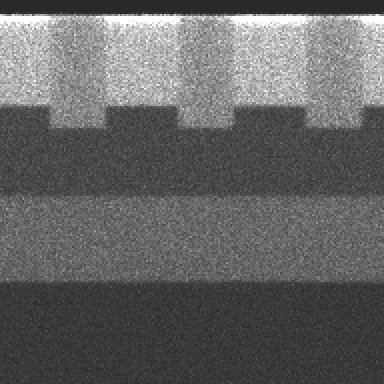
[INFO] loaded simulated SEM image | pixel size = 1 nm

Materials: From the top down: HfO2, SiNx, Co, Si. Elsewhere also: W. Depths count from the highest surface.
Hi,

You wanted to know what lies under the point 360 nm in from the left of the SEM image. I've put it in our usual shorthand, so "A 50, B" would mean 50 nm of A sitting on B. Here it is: W 112, SiNx 68, Co 86, Si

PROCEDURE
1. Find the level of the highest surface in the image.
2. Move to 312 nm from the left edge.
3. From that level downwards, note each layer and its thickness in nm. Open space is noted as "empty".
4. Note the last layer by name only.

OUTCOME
W 112, SiNx 68, Co 86, Si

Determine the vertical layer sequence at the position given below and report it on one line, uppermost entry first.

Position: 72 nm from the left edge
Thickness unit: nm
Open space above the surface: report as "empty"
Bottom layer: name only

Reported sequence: W 112, SiNx 68, Co 86, Si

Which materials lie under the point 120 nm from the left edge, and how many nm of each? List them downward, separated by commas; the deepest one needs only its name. HfO2 90, SiNx 90, Co 86, Si